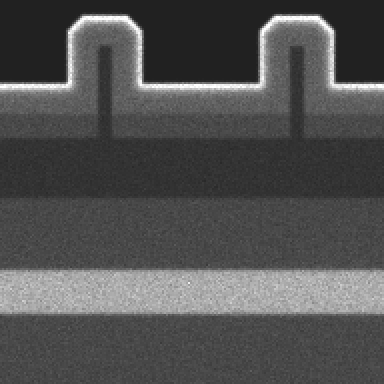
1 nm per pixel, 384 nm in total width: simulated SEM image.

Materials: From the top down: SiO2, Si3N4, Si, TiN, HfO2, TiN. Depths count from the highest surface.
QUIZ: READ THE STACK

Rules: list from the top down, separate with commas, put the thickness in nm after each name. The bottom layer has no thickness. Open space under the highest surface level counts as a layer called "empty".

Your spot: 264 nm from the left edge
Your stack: empty 10, SiO2 88, Si3N4 24, Si 60, TiN 72, HfO2 44, TiN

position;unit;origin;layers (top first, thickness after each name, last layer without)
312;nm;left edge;SiO2 98, Si3N4 24, Si 60, TiN 72, HfO2 44, TiN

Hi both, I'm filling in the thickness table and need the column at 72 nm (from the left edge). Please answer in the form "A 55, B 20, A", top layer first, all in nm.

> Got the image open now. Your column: empty 10, SiO2 88, Si3N4 24, Si 60, TiN 72, HfO2 44, TiN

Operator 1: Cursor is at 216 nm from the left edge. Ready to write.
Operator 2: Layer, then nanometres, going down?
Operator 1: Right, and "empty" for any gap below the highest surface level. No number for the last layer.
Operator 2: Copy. empty 68, SiO2 30, Si3N4 24, Si 60, TiN 72, HfO2 44, TiN